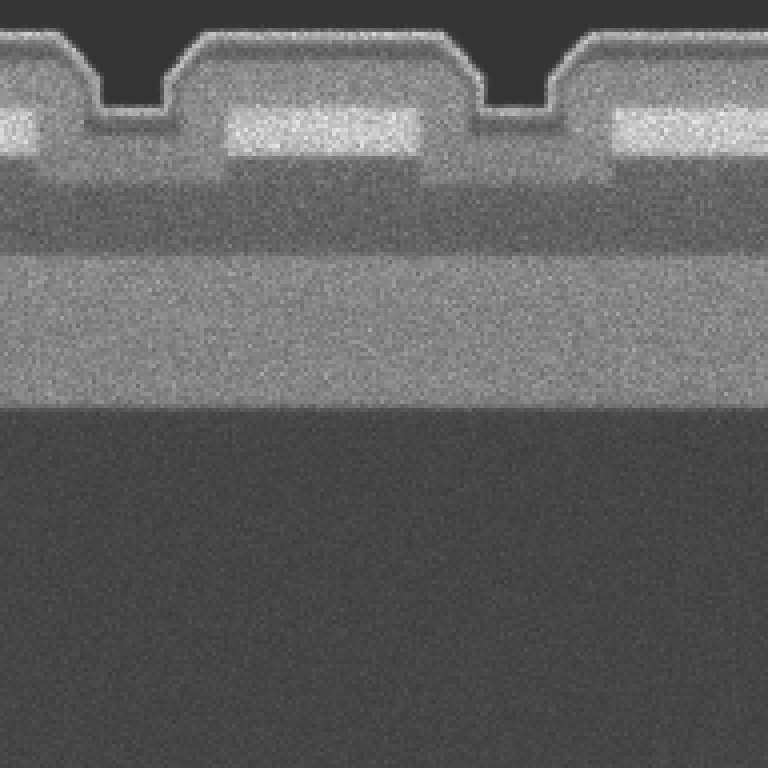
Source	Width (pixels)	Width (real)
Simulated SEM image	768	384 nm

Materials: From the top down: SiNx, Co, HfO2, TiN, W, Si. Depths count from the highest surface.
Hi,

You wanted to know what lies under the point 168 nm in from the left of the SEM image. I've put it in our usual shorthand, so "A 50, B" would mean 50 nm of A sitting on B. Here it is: SiNx 14, Co 24, HfO2 24, TiN 50, W 76, Si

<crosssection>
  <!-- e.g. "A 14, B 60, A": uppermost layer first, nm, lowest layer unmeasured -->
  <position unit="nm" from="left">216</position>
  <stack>SiNx 14, Co 62, TiN 36, W 76, Si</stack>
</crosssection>